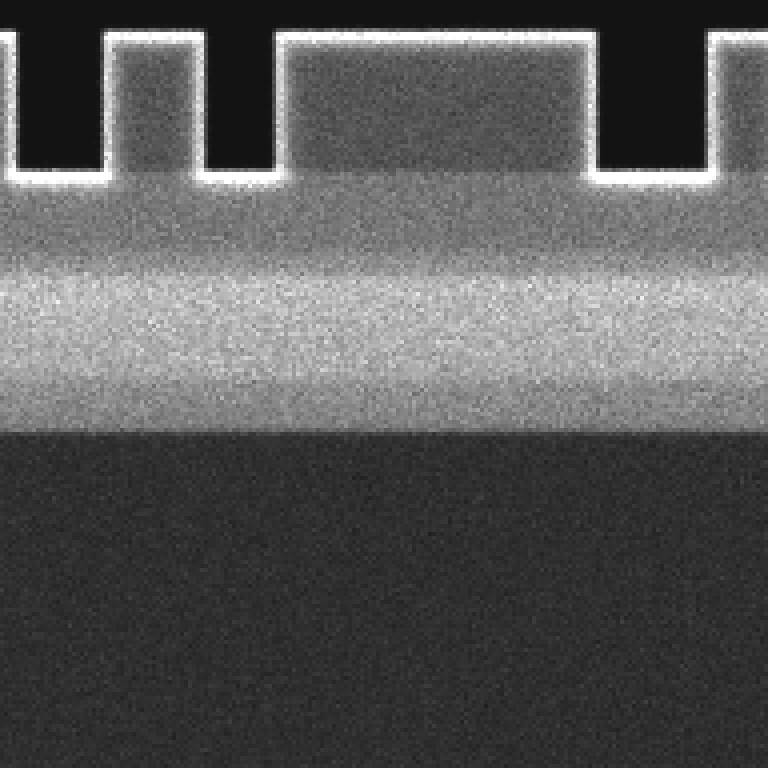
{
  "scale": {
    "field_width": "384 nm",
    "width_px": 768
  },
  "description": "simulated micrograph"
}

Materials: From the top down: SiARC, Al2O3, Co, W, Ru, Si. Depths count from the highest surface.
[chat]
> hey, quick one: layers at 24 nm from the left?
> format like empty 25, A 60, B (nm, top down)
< empty 70, Al2O3 40, Co 12, W 52, Ru 26, Si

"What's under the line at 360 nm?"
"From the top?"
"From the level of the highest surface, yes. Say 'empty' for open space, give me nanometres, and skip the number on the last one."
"SiARC 70, Al2O3 40, Co 12, W 52, Ru 26, Si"